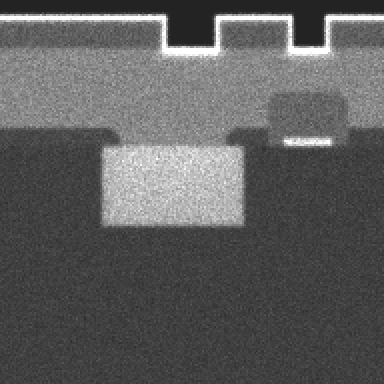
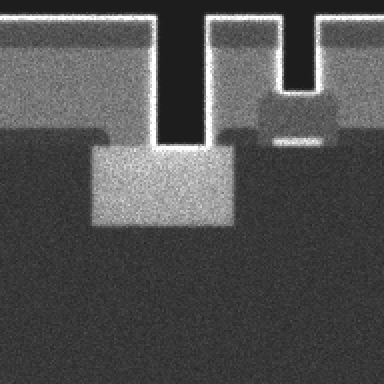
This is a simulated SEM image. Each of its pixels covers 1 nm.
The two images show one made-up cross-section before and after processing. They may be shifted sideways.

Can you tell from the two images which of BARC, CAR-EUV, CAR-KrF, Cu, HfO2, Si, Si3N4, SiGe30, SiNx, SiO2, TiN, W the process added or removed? Yes, it removed SiO2.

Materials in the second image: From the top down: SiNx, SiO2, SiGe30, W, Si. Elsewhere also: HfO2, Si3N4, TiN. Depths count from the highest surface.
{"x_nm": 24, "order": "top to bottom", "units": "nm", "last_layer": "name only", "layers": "SiNx 32, SiO2 80, SiGe30 18, Si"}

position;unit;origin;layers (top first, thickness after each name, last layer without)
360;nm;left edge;SiNx 32, SiO2 80, SiGe30 18, Si